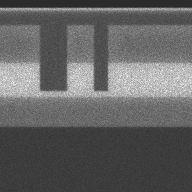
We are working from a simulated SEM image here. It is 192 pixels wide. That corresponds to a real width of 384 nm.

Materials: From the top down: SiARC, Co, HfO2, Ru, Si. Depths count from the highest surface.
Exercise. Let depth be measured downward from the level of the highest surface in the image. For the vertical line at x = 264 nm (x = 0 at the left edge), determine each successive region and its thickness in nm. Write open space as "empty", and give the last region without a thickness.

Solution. SiARC 34, Co 76, HfO2 68, Ru 60, Si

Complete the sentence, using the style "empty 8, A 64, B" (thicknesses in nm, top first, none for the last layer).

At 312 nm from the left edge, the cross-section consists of SiARC 34, Co 76, HfO2 68, Ru 60, Si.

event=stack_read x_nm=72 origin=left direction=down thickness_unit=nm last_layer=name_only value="SiARC 34, Co 76, HfO2 68, Ru 60, Si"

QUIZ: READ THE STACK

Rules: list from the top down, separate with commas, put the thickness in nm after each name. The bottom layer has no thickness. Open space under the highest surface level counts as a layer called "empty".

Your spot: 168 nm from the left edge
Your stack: SiARC 34, Co 76, HfO2 68, Ru 60, Si